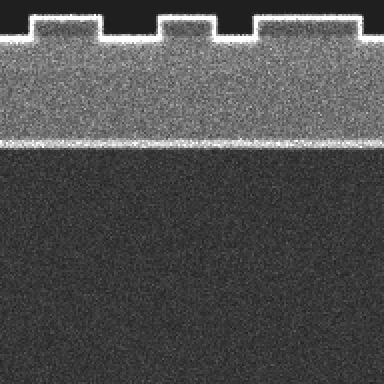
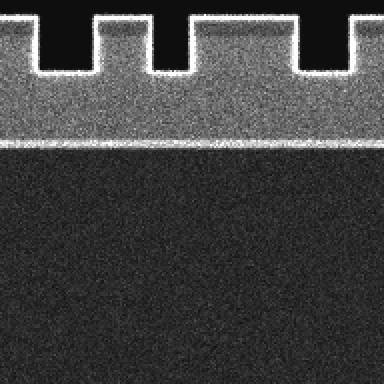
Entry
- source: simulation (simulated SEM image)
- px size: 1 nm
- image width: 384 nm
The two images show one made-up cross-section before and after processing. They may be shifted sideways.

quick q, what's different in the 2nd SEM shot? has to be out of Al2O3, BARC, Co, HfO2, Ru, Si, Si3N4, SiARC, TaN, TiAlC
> Al2O3 removed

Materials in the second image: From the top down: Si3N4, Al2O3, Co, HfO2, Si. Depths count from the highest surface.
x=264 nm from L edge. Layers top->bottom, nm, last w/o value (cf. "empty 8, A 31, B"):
Si3N4 20, Al2O3 36, Co 68, HfO2 8, Si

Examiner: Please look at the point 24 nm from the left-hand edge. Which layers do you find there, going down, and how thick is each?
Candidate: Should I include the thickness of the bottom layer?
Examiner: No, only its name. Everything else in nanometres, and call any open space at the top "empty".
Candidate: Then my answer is Si3N4 20, Al2O3 36, Co 68, HfO2 8, Si